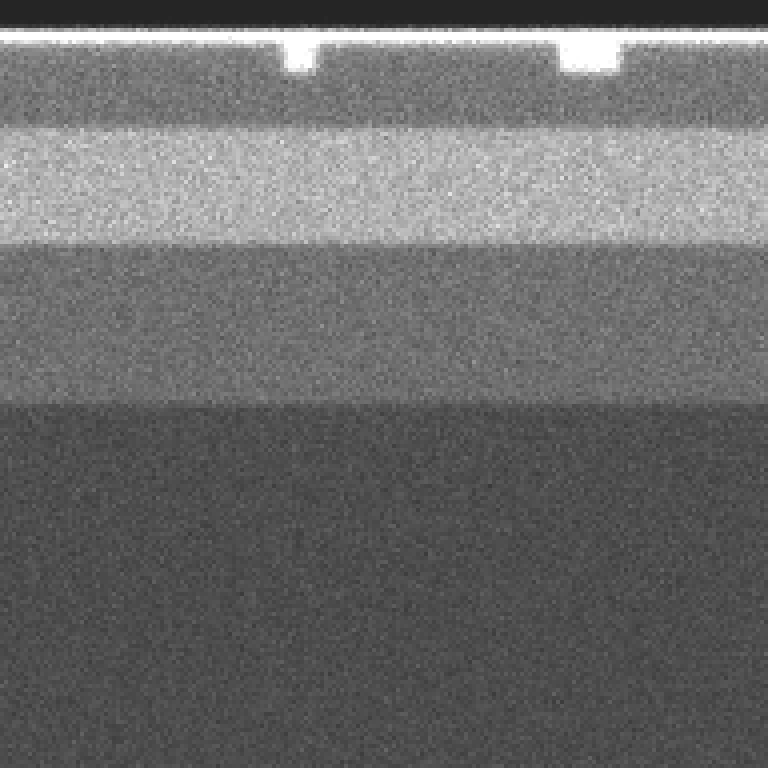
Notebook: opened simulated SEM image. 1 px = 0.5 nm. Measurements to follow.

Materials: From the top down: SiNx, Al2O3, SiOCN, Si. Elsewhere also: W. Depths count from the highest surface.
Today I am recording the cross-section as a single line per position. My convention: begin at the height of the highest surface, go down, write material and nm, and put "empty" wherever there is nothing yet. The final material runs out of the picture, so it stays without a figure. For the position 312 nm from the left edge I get SiNx 48, Al2O3 58, SiOCN 80, Si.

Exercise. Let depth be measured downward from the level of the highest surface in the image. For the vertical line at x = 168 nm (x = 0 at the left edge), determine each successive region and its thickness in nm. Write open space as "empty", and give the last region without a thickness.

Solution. SiNx 48, Al2O3 58, SiOCN 80, Si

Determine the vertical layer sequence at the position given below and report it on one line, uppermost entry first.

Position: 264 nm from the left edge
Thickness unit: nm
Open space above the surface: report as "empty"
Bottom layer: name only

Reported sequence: SiNx 48, Al2O3 58, SiOCN 80, Si